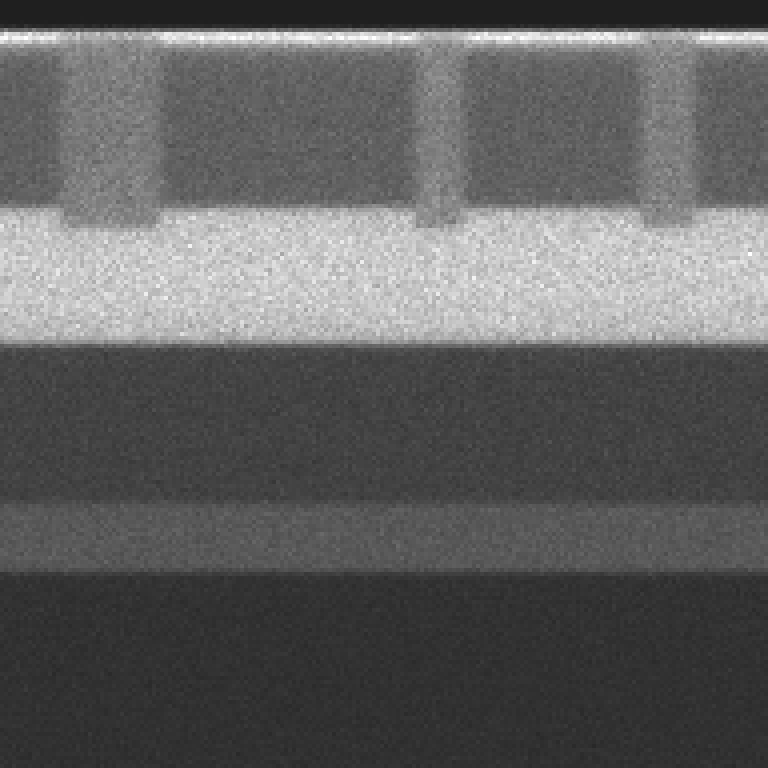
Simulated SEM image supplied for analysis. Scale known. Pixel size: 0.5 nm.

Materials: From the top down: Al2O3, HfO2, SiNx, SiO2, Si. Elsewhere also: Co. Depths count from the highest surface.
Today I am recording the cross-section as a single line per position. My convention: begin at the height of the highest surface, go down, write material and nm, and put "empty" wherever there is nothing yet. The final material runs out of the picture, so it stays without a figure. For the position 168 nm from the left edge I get Al2O3 88, HfO2 68, SiNx 80, SiO2 34, Si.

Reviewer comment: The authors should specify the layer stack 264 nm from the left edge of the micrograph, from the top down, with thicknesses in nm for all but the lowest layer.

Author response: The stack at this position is Al2O3 88, HfO2 68, SiNx 80, SiO2 34, Si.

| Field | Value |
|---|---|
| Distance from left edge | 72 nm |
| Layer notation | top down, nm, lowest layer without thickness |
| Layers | Co 98, HfO2 58, SiNx 80, SiO2 34, Si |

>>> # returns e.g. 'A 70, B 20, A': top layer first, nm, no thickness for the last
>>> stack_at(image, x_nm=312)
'Al2O3 88, HfO2 68, SiNx 80, SiO2 34, Si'